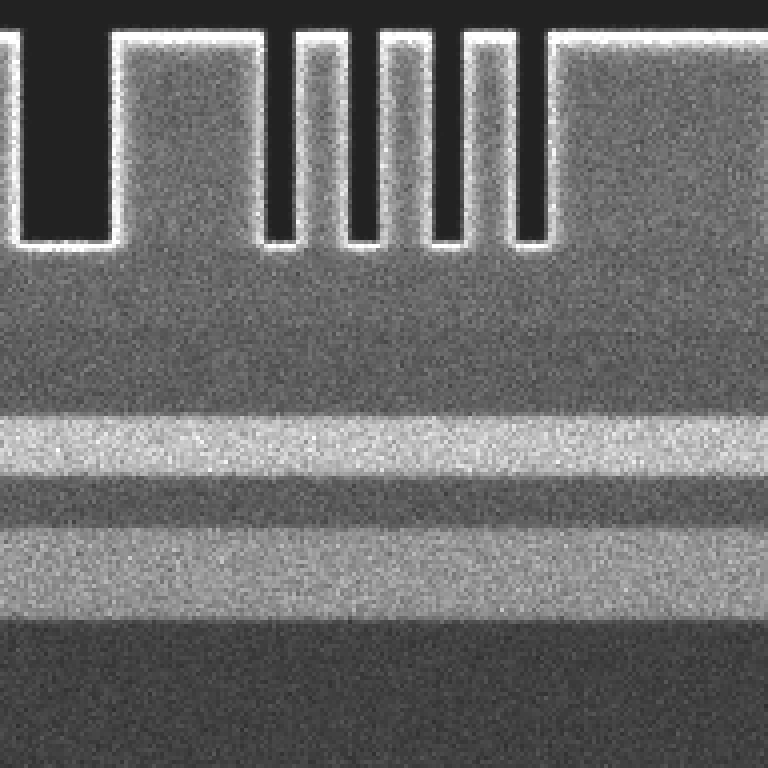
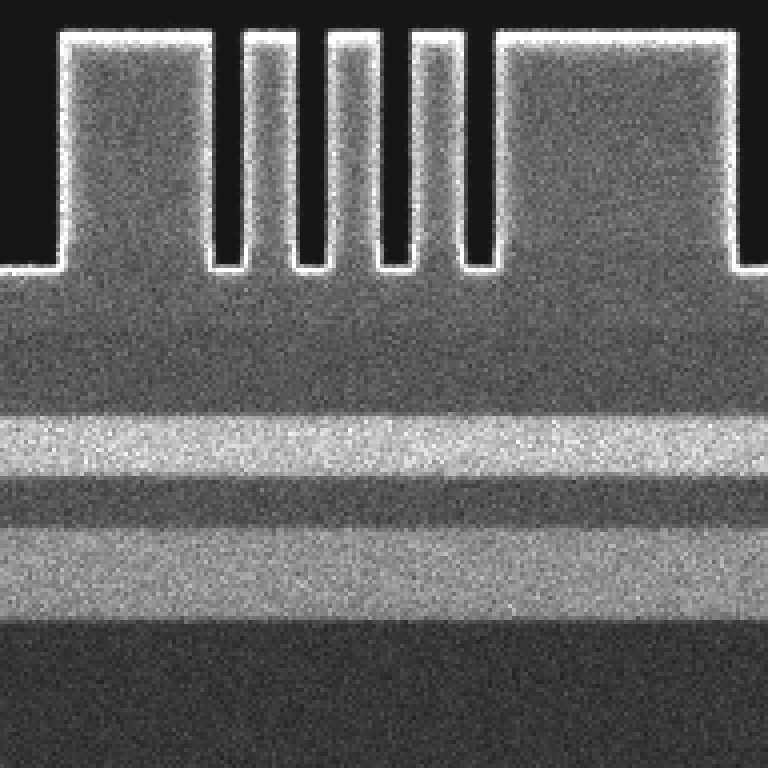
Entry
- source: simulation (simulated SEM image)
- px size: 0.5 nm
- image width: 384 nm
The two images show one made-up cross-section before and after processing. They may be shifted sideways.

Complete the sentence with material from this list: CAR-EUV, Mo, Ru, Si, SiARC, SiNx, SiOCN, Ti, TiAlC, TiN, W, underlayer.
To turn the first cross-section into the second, TiN must be removed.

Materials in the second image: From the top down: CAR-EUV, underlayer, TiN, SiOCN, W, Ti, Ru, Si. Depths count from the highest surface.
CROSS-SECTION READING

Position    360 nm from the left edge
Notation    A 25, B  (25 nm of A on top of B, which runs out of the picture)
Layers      CAR-EUV 56, underlayer 50, TiN 42, SiOCN 44, W 30, Ti 26, Ru 46, Si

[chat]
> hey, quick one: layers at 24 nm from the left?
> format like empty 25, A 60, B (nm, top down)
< empty 118, TiN 30, SiOCN 44, W 30, Ti 26, Ru 46, Si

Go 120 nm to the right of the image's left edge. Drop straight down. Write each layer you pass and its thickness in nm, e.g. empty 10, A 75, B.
empty 118, TiN 30, SiOCN 44, W 30, Ti 26, Ru 46, Si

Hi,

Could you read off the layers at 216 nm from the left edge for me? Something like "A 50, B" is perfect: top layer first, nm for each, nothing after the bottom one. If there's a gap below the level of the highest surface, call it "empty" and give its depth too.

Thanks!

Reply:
CAR-EUV 56, underlayer 50, TiN 42, SiOCN 44, W 30, Ti 26, Ru 46, Si